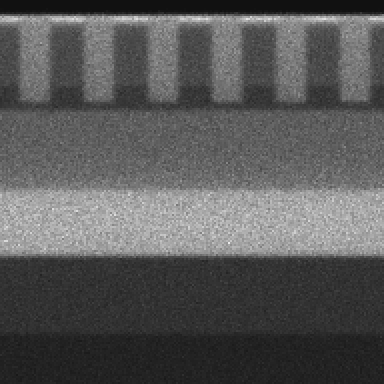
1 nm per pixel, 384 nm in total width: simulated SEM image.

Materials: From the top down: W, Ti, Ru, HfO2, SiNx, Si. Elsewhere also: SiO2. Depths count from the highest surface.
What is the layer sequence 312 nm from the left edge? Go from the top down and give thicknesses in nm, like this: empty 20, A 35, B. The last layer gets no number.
SiO2 70, Ti 24, Ru 80, HfO2 66, SiNx 78, Si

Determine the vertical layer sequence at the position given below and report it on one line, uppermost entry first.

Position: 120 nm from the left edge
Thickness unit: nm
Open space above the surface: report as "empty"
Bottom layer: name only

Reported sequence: SiO2 70, Ti 24, Ru 80, HfO2 66, SiNx 78, Si